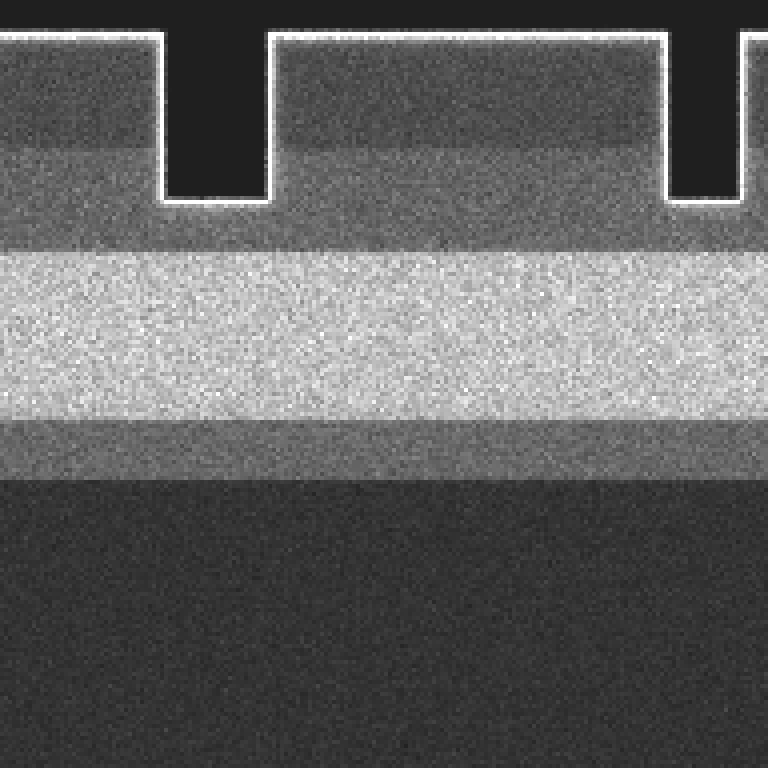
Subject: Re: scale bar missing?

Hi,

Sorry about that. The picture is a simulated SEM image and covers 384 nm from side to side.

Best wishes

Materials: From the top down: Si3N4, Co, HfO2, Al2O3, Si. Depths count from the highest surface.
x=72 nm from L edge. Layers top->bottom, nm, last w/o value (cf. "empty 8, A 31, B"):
Si3N4 58, Co 52, HfO2 84, Al2O3 30, Si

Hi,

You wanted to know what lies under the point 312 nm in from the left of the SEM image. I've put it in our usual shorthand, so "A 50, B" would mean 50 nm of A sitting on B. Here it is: Si3N4 58, Co 52, HfO2 84, Al2O3 30, Si